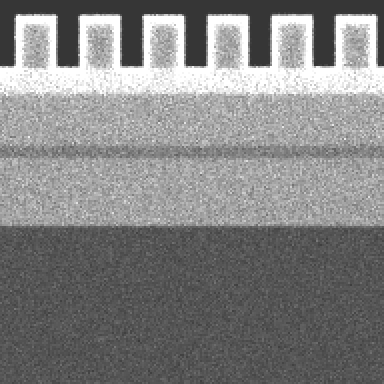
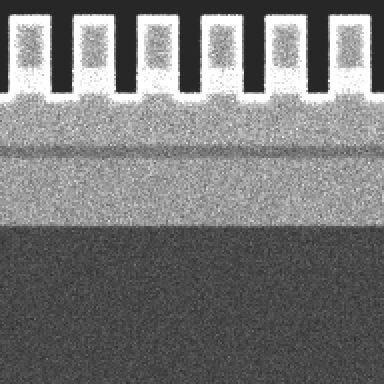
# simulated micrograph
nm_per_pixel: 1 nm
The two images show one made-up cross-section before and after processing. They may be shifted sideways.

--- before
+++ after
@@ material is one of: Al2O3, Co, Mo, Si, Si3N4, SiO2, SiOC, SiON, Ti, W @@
W removed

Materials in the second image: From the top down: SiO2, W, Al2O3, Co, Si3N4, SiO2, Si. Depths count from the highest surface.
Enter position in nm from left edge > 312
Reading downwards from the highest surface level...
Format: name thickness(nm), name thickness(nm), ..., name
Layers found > empty 78, Al2O3 34, Co 18, Si3N4 12, SiO2 68, Si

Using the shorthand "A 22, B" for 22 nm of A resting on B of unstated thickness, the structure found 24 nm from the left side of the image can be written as SiO2 52, W 26, Al2O3 34, Co 18, Si3N4 12, SiO2 68, Si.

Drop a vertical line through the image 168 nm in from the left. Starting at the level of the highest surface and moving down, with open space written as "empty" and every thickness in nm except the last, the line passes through SiO2 52, W 26, Al2O3 34, Co 18, Si3N4 12, SiO2 68, Si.